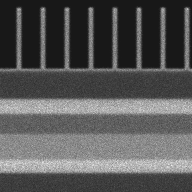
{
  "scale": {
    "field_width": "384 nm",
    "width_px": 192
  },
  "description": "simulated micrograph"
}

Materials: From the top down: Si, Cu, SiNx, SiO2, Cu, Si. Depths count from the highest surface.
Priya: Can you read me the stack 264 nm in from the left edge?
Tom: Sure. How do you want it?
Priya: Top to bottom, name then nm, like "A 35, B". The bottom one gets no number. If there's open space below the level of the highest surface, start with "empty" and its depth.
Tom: empty 122, Si 60, Cu 30, SiNx 40, SiO2 52, Cu 26, Si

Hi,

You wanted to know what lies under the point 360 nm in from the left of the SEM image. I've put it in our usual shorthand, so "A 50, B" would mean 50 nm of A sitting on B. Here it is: empty 122, Si 60, Cu 30, SiNx 40, SiO2 52, Cu 26, Si